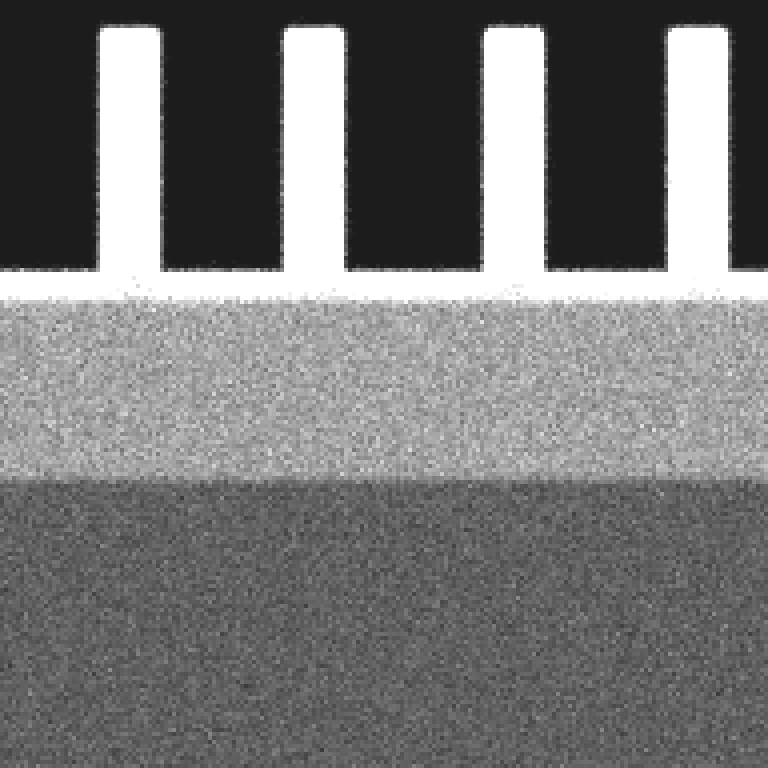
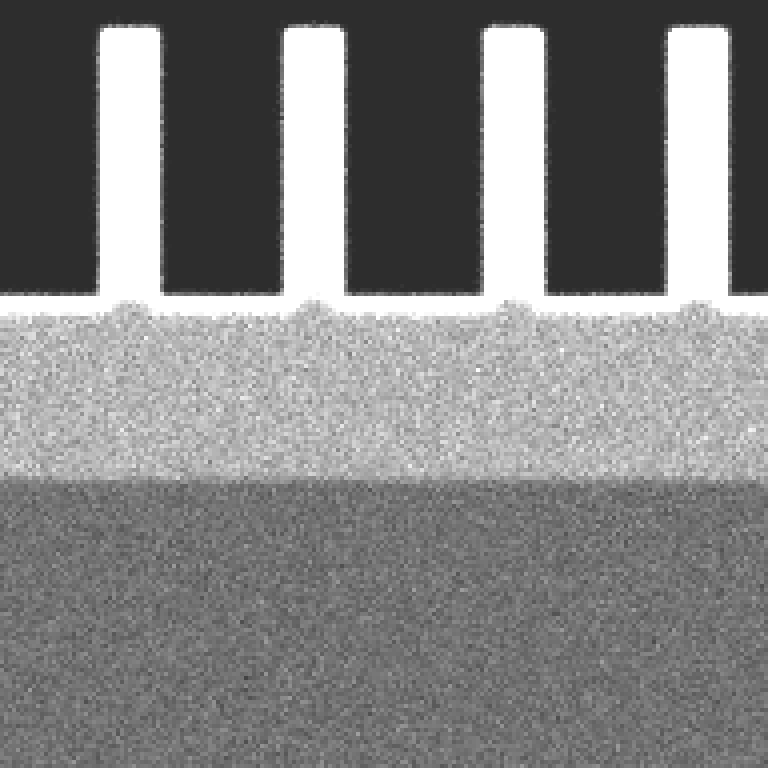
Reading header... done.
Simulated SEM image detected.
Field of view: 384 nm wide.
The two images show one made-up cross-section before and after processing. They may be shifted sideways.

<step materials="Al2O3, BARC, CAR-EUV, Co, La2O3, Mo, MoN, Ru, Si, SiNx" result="removed Co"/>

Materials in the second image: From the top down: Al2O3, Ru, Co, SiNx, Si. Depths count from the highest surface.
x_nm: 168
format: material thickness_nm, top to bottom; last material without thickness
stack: Al2O3 42, Ru 80, Co 12, SiNx 90, Si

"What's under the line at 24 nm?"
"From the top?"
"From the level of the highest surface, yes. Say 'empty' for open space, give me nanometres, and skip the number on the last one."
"empty 134, SiNx 90, Si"